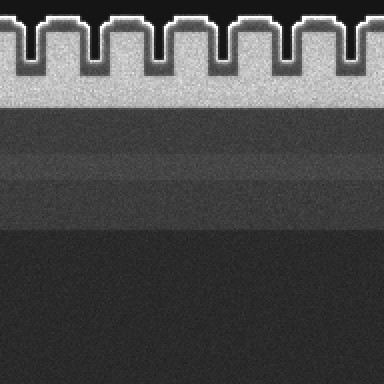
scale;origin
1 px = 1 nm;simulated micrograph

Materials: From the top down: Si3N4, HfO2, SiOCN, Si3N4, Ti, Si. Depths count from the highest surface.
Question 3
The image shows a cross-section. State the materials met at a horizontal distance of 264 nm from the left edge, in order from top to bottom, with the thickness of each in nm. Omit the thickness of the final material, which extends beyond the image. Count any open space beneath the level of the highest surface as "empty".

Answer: Si3N4 16, HfO2 76, SiOCN 46, Si3N4 26, Ti 50, Si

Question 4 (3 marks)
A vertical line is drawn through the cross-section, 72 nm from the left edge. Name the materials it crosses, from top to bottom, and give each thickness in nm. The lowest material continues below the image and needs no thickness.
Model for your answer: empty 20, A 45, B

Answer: Si3N4 16, HfO2 76, SiOCN 46, Si3N4 26, Ti 50, Si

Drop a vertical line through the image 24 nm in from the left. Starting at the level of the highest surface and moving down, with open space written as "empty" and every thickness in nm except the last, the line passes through empty 10, Si3N4 50, HfO2 32, SiOCN 46, Si3N4 26, Ti 50, Si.